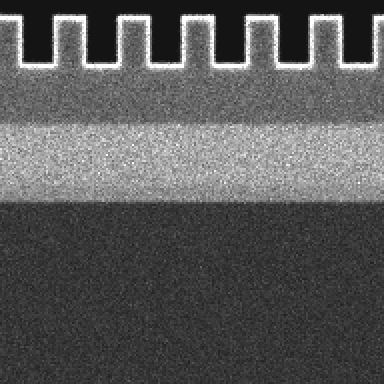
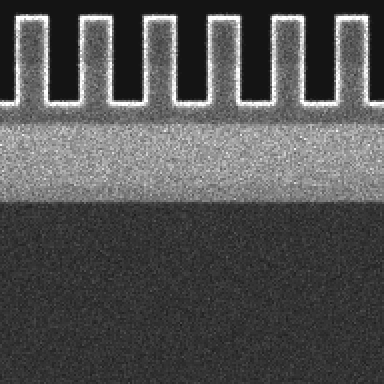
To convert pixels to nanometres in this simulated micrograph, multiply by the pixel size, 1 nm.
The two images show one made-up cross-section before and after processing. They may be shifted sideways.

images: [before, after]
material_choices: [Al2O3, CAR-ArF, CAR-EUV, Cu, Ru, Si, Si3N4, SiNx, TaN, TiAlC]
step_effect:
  removed: Si3N4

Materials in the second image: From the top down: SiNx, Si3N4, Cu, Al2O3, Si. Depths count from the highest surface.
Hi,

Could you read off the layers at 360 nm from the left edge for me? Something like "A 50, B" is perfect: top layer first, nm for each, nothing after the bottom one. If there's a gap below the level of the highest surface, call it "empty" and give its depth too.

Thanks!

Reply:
SiNx 48, Si3N4 60, Cu 62, Al2O3 16, Si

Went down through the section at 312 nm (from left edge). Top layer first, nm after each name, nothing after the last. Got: empty 86, Si3N4 22, Cu 62, Al2O3 16, Si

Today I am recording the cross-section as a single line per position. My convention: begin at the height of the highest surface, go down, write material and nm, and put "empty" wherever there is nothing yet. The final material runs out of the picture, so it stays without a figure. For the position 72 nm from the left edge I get empty 86, Si3N4 22, Cu 62, Al2O3 16, Si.